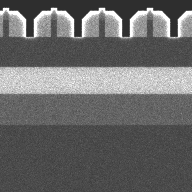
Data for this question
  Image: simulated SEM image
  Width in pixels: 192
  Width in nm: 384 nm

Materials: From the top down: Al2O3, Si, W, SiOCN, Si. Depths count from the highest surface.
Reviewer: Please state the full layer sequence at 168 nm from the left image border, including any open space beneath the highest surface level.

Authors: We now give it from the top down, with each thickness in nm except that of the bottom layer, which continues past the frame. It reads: empty 18, Al2O3 40, Si 60, W 54, SiOCN 62, Si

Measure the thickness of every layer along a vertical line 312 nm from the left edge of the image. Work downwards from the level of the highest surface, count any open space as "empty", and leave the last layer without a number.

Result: empty 6, Al2O3 52, Si 60, W 54, SiOCN 62, Si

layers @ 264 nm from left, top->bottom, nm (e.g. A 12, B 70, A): empty 18, Al2O3 40, Si 60, W 54, SiOCN 62, Si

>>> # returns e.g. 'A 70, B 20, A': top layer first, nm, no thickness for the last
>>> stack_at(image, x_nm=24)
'empty 6, Al2O3 52, Si 60, W 54, SiOCN 62, Si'